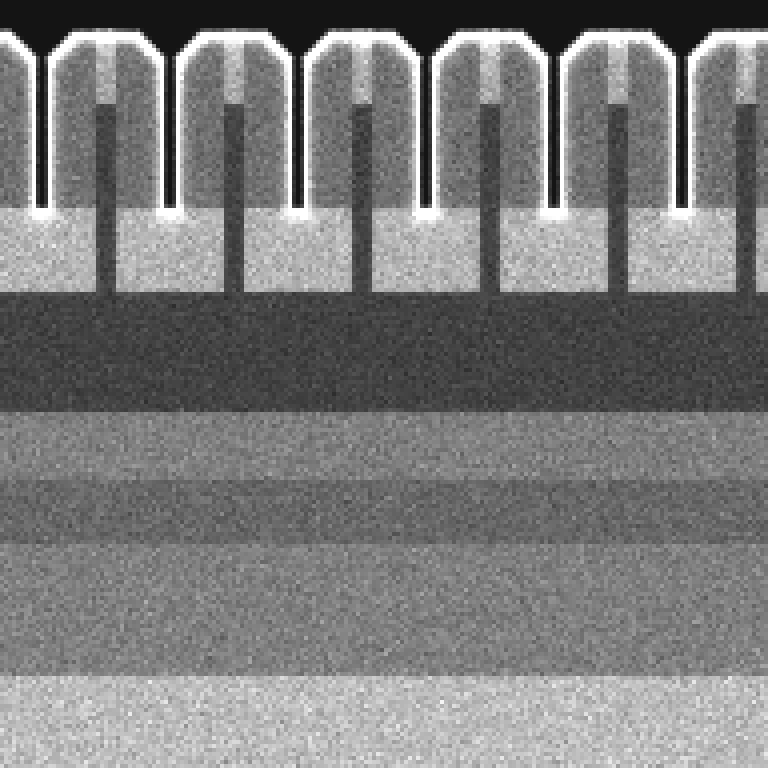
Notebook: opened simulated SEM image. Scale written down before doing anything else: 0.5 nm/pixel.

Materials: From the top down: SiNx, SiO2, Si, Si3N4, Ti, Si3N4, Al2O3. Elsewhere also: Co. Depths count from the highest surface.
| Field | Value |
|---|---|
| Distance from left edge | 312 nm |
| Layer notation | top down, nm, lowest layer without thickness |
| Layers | Co 36, Si 154, Si3N4 34, Ti 32, Si3N4 66, Al2O3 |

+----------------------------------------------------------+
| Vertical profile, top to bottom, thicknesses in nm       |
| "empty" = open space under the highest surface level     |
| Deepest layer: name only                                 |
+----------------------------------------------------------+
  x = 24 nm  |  empty 12, SiNx 76, SiO2 42, Si 60, Si3N4 34, Ti 32, Si3N4 66, Al2O3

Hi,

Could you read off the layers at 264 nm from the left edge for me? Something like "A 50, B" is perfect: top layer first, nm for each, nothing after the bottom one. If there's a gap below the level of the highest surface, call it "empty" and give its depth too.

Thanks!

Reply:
empty 4, SiNx 84, SiO2 42, Si 60, Si3N4 34, Ti 32, Si3N4 66, Al2O3